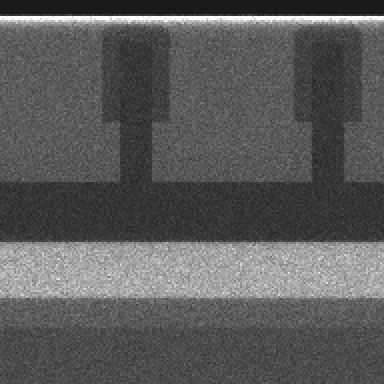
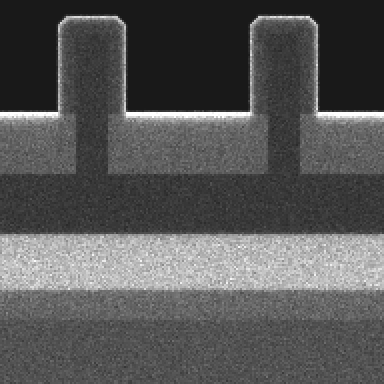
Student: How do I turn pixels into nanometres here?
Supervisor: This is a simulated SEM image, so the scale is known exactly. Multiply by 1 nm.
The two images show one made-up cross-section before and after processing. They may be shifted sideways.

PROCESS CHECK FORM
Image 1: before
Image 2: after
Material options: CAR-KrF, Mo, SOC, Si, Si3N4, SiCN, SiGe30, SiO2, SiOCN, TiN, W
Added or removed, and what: removed, SOC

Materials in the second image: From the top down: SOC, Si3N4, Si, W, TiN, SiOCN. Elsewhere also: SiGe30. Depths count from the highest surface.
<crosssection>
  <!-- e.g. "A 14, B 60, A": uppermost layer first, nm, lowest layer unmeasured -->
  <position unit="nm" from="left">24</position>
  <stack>empty 96, SOC 34, Si3N4 28, Si 60, W 56, TiN 30, SiOCN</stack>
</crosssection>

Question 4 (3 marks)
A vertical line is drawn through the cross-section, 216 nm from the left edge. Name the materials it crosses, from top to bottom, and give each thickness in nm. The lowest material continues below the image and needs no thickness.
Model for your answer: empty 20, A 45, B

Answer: empty 96, SOC 34, Si3N4 28, Si 60, W 56, TiN 30, SiOCN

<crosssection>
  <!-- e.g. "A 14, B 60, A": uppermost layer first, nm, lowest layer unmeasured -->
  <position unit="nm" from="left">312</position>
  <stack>empty 4, SiGe30 94, Si3N4 60, Si 60, W 56, TiN 30, SiOCN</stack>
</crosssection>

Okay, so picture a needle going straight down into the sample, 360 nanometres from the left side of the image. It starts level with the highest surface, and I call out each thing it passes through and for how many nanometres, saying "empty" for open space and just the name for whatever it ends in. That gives empty 96, SOC 34, Si3N4 28, Si 60, W 56, TiN 30, SiOCN